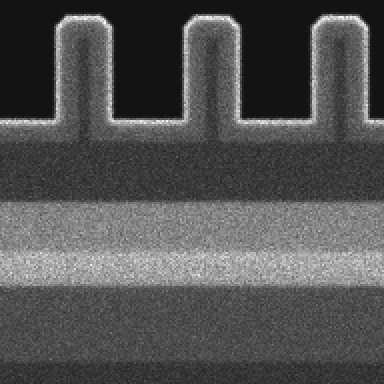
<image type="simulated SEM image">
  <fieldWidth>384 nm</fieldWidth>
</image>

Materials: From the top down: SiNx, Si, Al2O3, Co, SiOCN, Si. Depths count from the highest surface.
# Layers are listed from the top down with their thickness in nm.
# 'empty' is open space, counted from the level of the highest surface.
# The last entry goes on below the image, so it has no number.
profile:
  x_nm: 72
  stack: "SiNx 126, Si 60, Al2O3 50, Co 34, SiOCN 76, Si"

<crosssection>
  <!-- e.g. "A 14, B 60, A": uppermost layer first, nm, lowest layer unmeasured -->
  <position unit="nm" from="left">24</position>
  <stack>empty 104, SiNx 22, Si 60, Al2O3 50, Co 34, SiOCN 76, Si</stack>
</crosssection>